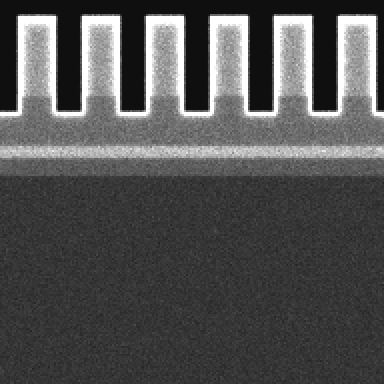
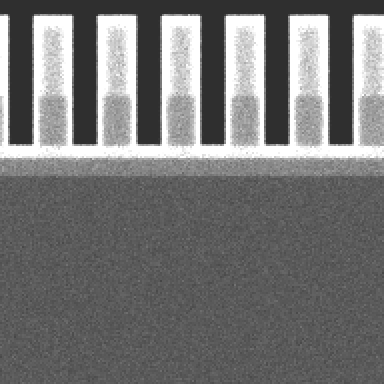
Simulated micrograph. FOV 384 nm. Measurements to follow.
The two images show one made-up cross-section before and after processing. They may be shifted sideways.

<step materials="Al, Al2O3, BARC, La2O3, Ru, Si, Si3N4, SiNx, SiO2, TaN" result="removed Si3N4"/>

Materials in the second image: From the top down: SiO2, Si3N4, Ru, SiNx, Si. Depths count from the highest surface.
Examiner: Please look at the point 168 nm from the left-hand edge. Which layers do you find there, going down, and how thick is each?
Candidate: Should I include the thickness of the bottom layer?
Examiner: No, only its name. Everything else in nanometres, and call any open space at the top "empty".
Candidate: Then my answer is SiO2 80, Si3N4 50, Ru 12, SiNx 18, Si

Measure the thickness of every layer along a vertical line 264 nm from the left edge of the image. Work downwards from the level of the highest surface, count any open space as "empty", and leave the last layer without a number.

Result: empty 130, Ru 12, SiNx 18, Si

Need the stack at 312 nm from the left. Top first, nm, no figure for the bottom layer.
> SiO2 80, Si3N4 50, Ru 12, SiNx 18, Si